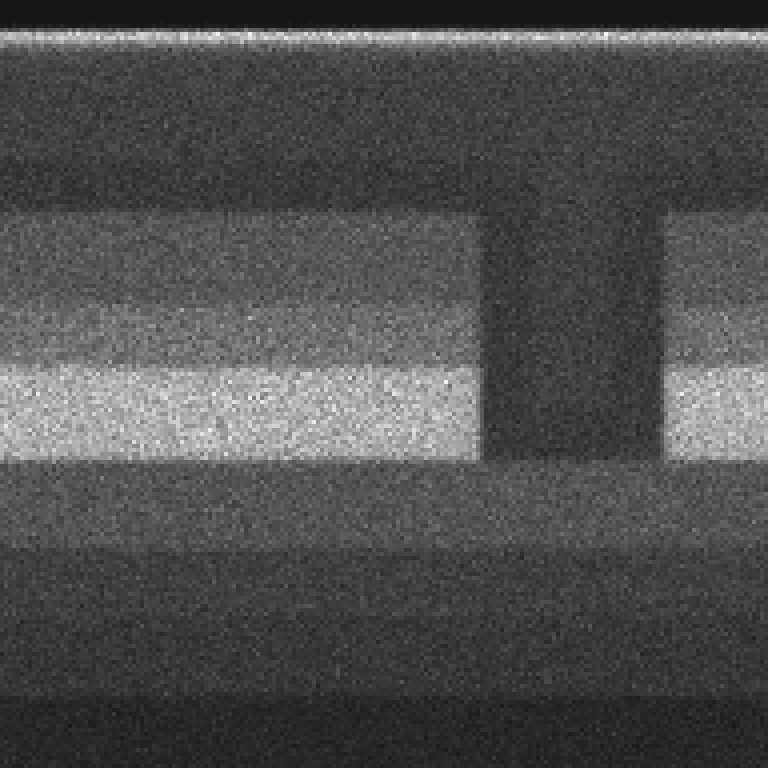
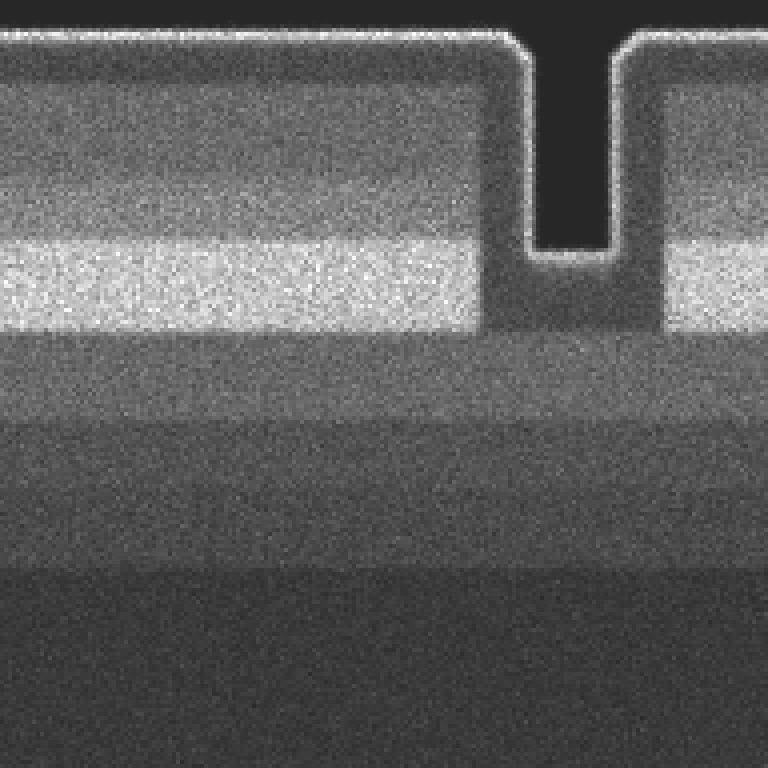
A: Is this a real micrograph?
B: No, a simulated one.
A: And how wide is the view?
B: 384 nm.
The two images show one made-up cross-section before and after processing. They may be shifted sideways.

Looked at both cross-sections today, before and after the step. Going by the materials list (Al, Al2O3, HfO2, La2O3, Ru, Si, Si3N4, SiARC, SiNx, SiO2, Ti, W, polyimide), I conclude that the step removed SiARC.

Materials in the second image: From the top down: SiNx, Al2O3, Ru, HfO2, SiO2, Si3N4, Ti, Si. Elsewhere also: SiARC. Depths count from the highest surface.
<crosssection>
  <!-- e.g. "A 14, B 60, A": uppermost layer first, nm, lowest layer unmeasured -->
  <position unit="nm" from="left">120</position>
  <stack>SiNx 26, Al2O3 46, Ru 32, HfO2 46, SiO2 44, Si3N4 34, Ti 40, Si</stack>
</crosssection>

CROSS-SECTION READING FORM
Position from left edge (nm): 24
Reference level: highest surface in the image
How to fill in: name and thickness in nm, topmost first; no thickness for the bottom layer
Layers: SiNx 26, Al2O3 46, Ru 32, HfO2 46, SiO2 44, Si3N4 34, Ti 40, Si